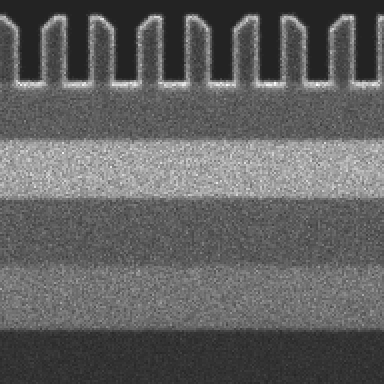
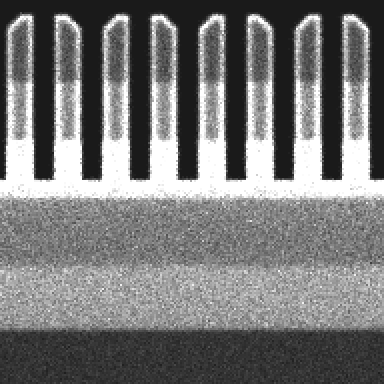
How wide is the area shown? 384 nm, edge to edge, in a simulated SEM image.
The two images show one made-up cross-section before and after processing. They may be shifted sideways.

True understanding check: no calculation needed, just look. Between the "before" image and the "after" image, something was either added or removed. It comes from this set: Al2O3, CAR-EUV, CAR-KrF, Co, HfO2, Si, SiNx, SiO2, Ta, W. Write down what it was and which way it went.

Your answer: Al2O3 and HfO2 (removed)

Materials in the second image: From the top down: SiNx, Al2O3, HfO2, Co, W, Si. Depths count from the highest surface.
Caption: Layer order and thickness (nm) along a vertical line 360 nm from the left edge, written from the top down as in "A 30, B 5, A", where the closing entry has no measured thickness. empty 6, SiNx 60, Al2O3 58, HfO2 58, Co 68, W 64, Si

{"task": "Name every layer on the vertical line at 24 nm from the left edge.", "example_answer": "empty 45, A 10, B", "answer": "SiNx 66, Al2O3 58, HfO2 58, Co 68, W 64, Si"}